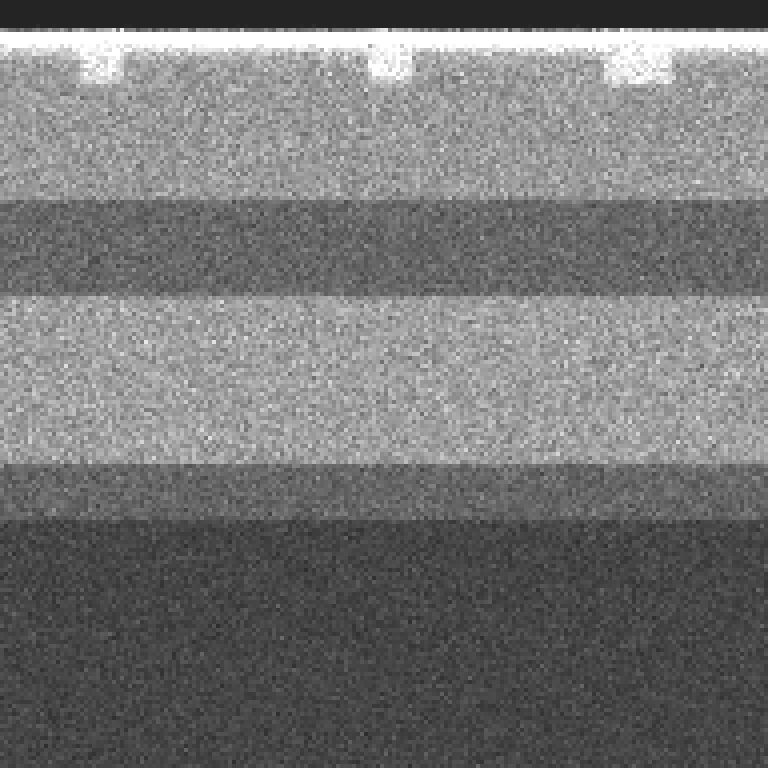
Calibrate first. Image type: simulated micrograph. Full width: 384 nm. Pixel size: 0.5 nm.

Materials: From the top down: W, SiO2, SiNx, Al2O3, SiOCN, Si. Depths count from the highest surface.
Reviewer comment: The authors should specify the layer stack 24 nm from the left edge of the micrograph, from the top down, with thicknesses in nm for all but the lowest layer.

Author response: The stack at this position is SiO2 84, SiNx 48, Al2O3 84, SiOCN 28, Si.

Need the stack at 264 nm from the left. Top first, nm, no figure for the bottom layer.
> SiO2 84, SiNx 48, Al2O3 84, SiOCN 28, Si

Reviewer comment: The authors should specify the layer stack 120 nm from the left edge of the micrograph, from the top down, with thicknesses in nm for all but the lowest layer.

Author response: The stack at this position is SiO2 84, SiNx 48, Al2O3 84, SiOCN 28, Si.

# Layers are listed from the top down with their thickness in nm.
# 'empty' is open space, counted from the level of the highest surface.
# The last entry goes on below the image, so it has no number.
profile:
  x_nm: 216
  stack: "SiO2 84, SiNx 48, Al2O3 84, SiOCN 28, Si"